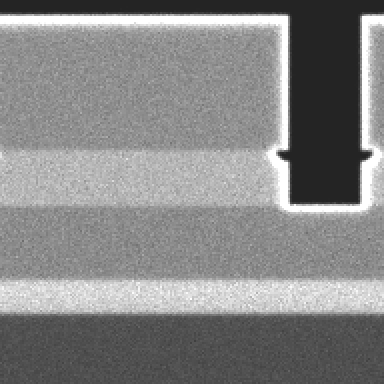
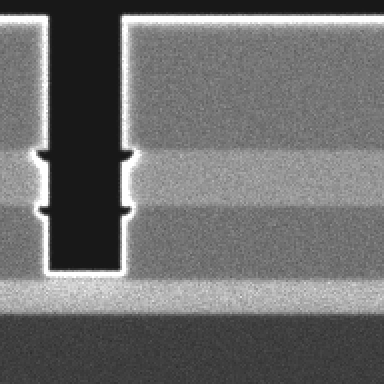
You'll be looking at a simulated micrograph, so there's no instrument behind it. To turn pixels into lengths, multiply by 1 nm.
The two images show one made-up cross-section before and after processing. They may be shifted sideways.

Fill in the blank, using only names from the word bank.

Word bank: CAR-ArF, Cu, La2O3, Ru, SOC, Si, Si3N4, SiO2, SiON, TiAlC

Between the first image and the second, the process removed Si3N4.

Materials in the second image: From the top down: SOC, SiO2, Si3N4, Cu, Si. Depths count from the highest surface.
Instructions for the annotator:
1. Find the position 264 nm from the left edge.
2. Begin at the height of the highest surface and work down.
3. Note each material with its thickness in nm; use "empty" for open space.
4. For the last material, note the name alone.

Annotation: SOC 134, SiO2 56, Si3N4 74, Cu 34, Si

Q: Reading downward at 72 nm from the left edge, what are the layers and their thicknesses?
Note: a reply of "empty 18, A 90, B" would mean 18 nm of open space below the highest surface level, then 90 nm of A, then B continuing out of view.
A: empty 256, Si3N4 8, Cu 34, Si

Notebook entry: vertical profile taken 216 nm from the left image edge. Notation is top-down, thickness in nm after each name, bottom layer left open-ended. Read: SOC 134, SiO2 56, Si3N4 74, Cu 34, Si